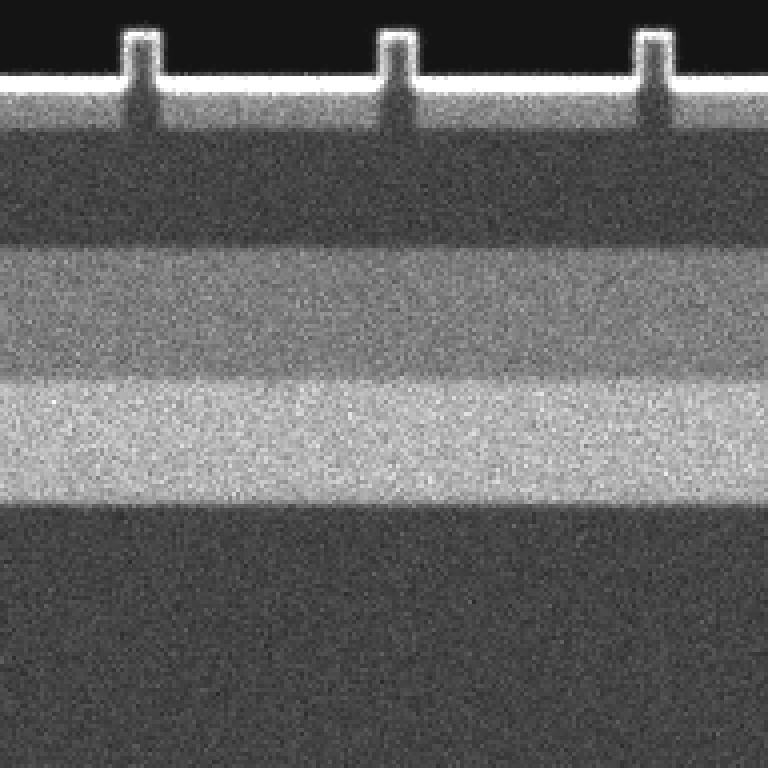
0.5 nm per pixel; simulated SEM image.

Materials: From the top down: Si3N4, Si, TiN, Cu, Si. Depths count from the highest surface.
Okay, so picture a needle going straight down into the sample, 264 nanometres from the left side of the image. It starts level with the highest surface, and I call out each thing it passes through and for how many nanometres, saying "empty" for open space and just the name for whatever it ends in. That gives empty 24, Si3N4 24, Si 60, TiN 66, Cu 62, Si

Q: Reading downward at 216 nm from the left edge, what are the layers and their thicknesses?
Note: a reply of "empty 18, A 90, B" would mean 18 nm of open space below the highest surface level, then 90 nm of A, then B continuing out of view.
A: empty 24, Si3N4 24, Si 60, TiN 66, Cu 62, Si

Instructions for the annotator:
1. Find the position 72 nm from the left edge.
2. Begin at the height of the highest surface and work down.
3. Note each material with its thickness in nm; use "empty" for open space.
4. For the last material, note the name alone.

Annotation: Si 108, TiN 66, Cu 62, Si